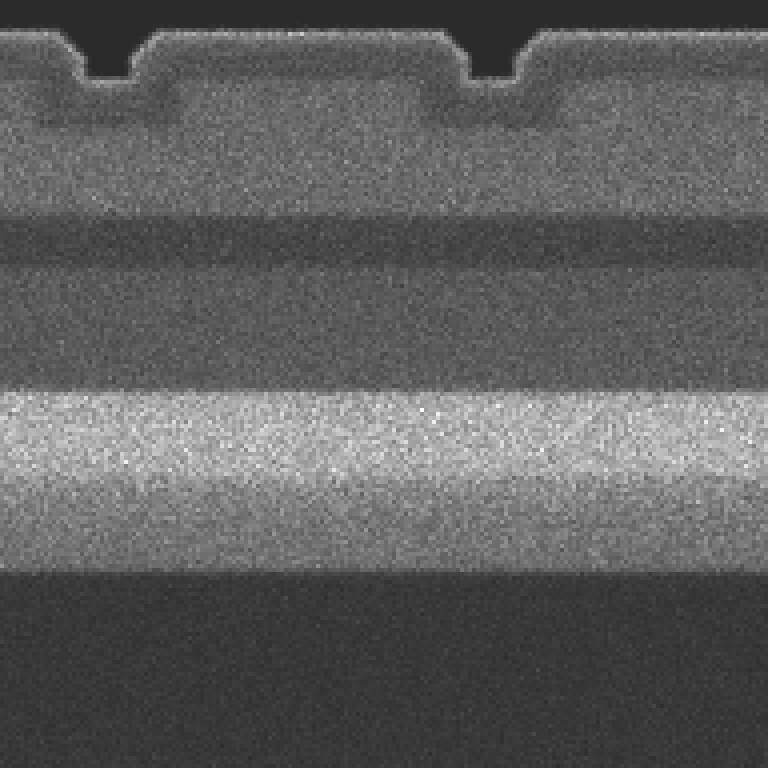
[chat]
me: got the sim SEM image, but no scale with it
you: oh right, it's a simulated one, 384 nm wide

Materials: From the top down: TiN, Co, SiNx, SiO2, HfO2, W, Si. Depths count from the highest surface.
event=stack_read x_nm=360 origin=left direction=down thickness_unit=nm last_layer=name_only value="TiN 24, Co 68, SiNx 26, SiO2 62, HfO2 42, W 48, Si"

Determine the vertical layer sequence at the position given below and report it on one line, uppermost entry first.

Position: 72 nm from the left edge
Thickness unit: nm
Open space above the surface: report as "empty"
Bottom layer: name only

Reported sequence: empty 6, TiN 42, Co 44, SiNx 26, SiO2 62, HfO2 42, W 48, Si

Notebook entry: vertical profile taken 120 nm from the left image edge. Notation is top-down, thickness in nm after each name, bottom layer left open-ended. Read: TiN 24, Co 68, SiNx 26, SiO2 62, HfO2 42, W 48, Si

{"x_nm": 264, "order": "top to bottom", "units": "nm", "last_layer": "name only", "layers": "empty 6, TiN 42, Co 44, SiNx 26, SiO2 62, HfO2 42, W 48, Si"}